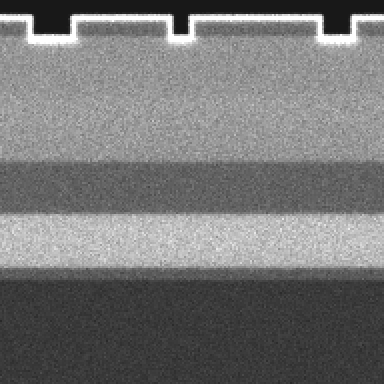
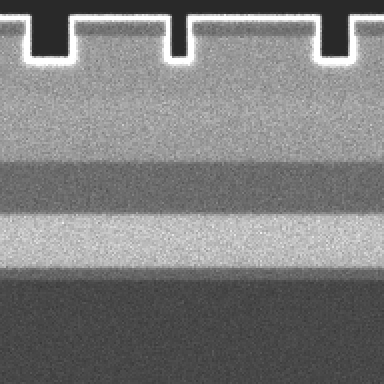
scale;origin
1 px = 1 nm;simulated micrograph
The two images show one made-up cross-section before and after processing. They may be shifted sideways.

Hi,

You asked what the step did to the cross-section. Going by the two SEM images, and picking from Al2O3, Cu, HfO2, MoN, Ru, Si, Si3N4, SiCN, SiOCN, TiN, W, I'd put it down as Al2O3, removed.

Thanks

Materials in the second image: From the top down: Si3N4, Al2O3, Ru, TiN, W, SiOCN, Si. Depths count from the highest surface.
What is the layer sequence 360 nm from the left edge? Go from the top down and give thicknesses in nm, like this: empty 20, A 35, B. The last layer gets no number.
Si3N4 20, Al2O3 60, Ru 66, TiN 52, W 54, SiOCN 12, Si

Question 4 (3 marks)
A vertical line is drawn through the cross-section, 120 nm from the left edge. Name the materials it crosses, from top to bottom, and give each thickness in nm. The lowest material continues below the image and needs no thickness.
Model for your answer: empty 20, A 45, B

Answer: Si3N4 20, Al2O3 60, Ru 66, TiN 52, W 54, SiOCN 12, Si